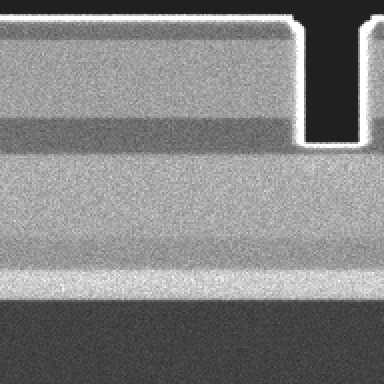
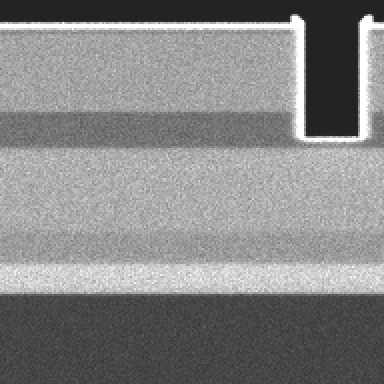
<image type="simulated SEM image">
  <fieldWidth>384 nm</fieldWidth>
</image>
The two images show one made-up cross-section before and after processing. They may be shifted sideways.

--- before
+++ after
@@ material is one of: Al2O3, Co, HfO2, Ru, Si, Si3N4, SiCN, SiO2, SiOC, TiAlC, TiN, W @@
Si3N4 removed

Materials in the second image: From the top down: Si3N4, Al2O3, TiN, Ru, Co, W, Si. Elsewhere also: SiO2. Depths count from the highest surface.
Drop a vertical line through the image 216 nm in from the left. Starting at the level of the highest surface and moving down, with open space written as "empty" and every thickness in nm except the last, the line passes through empty 8, Si3N4 10, Al2O3 78, TiN 36, Ru 84, Co 32, W 30, Si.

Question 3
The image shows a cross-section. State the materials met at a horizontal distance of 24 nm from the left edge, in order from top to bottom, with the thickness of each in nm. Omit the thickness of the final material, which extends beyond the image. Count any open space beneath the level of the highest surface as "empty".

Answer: empty 8, Si3N4 10, Al2O3 78, TiN 36, Ru 84, Co 32, W 30, Si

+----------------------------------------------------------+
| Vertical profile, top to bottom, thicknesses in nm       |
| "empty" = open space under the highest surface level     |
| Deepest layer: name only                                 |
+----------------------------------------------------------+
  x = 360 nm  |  empty 6, SiO2 116, TiN 10, Ru 84, Co 32, W 30, Si